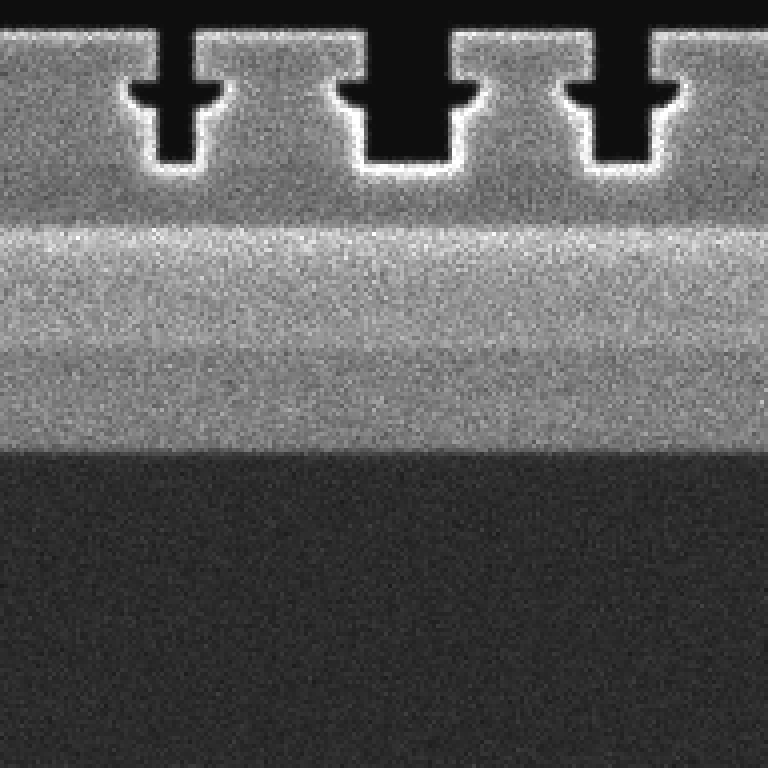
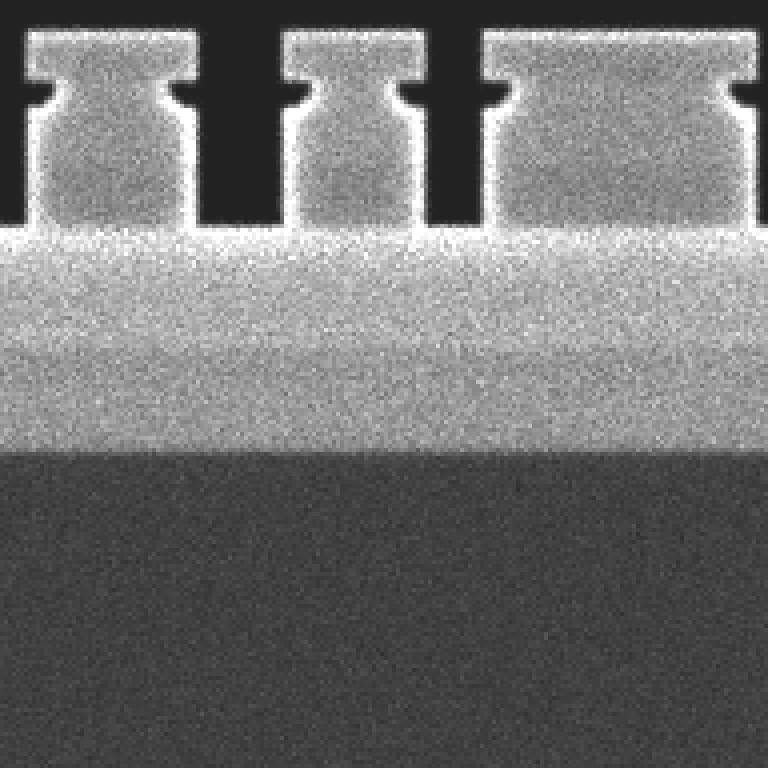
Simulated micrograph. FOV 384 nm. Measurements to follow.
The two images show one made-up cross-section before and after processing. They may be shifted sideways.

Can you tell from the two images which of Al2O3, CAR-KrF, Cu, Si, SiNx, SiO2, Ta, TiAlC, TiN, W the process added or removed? Yes, it removed SiO2.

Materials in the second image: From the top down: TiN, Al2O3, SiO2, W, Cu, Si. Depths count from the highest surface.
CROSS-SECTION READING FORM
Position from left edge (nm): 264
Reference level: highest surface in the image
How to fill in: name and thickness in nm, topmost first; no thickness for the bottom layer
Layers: TiN 24, Al2O3 42, SiO2 32, W 60, Cu 52, Si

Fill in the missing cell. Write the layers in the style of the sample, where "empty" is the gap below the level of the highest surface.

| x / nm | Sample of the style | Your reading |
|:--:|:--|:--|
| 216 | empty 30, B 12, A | empty 98, W 60, Cu 52, Si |